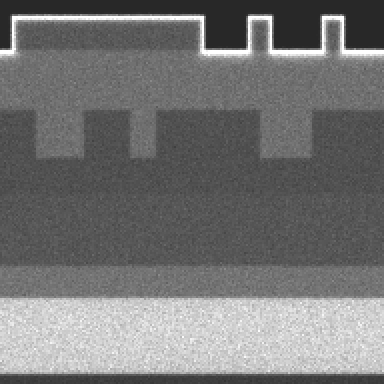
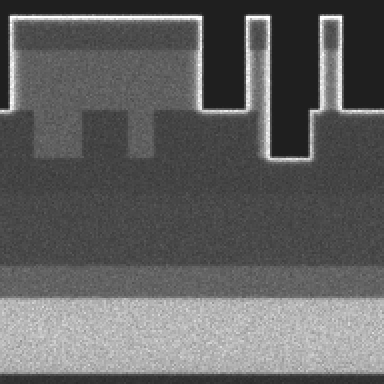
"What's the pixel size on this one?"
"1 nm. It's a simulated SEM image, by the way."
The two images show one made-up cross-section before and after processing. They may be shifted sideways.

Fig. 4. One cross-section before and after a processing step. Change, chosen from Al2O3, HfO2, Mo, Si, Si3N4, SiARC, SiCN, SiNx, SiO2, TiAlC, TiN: SiO2 removed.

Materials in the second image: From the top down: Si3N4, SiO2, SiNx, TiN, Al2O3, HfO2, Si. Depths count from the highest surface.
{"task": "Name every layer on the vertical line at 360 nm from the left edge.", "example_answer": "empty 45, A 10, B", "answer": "empty 94, SiNx 84, TiN 72, Al2O3 32, HfO2 76, Si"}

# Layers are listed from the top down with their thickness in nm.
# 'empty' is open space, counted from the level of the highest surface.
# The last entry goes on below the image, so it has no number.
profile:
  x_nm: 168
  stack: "Si3N4 34, SiO2 60, SiNx 84, TiN 72, Al2O3 32, HfO2 76, Si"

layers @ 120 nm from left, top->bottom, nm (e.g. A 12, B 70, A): Si3N4 34, SiO2 60, SiNx 84, TiN 72, Al2O3 32, HfO2 76, Si